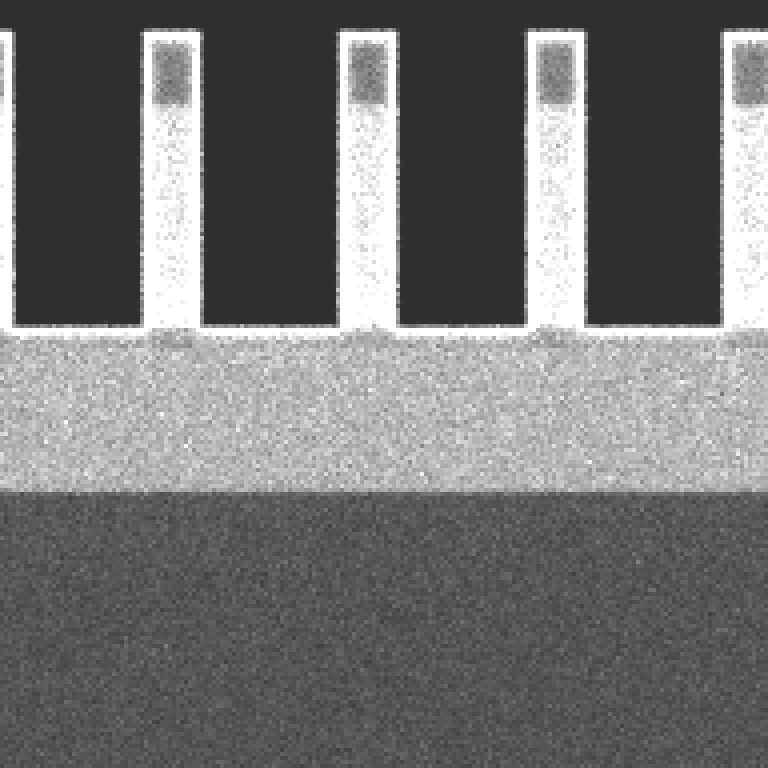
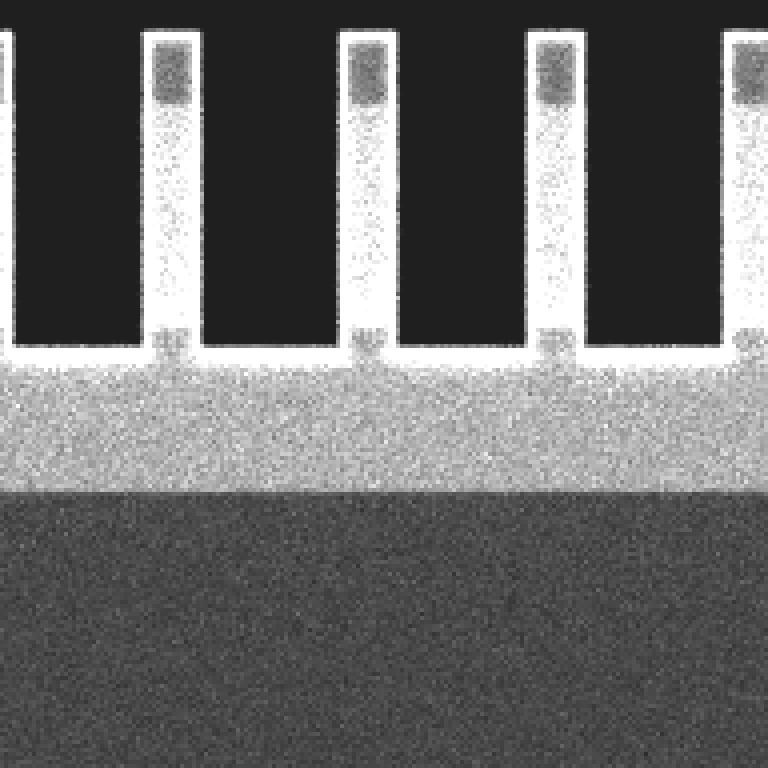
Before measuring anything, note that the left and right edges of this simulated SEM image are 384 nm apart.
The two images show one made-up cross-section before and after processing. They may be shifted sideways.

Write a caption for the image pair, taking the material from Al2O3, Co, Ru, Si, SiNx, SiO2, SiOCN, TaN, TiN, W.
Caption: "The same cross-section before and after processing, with TiN removed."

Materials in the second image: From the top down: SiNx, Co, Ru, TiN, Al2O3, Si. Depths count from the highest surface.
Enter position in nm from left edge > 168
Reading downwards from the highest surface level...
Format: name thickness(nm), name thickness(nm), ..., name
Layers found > empty 158, Al2O3 72, Si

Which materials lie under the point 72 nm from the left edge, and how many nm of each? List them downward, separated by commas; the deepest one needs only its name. SiNx 36, Co 98, Ru 14, TiN 10, Al2O3 72, Si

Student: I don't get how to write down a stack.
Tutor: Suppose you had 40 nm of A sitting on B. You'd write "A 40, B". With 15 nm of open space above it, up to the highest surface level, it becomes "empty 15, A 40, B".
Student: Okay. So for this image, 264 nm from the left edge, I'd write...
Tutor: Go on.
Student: SiNx 36, Co 98, Ru 14, TiN 10, Al2O3 72, Si